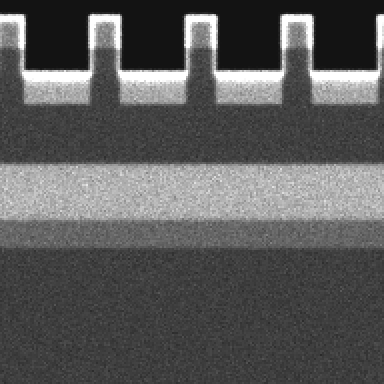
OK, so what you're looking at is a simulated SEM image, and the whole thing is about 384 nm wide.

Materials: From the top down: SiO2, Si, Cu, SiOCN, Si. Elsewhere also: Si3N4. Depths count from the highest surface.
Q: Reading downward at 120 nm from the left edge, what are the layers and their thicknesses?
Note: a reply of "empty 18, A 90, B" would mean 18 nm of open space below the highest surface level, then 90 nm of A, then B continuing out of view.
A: empty 56, SiO2 32, Si 60, Cu 56, SiOCN 28, Si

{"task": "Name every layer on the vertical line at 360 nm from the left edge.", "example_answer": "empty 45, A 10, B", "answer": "empty 56, SiO2 32, Si 60, Cu 56, SiOCN 28, Si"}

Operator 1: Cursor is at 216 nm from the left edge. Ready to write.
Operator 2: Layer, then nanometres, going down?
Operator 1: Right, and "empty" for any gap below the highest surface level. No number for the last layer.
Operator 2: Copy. empty 56, SiO2 32, Si 60, Cu 56, SiOCN 28, Si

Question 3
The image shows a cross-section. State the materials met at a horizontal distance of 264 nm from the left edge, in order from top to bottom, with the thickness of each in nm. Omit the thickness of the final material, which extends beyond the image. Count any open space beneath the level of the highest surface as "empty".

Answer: empty 56, SiO2 32, Si 60, Cu 56, SiOCN 28, Si